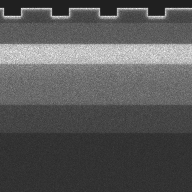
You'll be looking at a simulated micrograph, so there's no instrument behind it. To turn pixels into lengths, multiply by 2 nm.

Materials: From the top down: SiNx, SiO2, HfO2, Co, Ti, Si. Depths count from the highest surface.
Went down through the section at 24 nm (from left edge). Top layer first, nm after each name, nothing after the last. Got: empty 16, SiNx 14, SiO2 42, HfO2 40, Co 82, Ti 56, Si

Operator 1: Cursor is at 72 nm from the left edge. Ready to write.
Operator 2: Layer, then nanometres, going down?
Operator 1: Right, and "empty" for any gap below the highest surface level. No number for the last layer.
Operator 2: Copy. SiNx 30, SiO2 42, HfO2 40, Co 82, Ti 56, Si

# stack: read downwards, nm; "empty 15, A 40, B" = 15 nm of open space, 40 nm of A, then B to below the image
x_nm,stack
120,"empty 16, SiNx 14, SiO2 42, HfO2 40, Co 82, Ti 56, Si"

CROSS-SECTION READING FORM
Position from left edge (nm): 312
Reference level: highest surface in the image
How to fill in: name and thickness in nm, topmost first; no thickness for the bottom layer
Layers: empty 16, SiNx 14, SiO2 42, HfO2 40, Co 82, Ti 56, Si